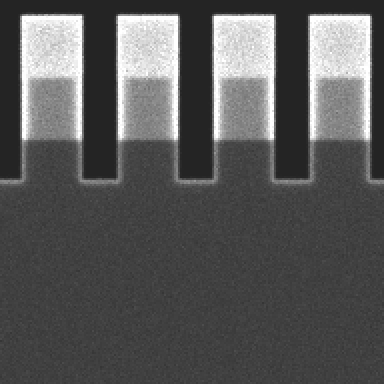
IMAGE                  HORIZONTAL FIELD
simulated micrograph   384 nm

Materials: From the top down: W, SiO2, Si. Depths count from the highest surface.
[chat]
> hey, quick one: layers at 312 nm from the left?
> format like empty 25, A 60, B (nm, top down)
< W 62, SiO2 62, Si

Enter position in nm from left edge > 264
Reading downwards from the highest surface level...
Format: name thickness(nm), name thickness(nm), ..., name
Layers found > W 62, SiO2 62, Si